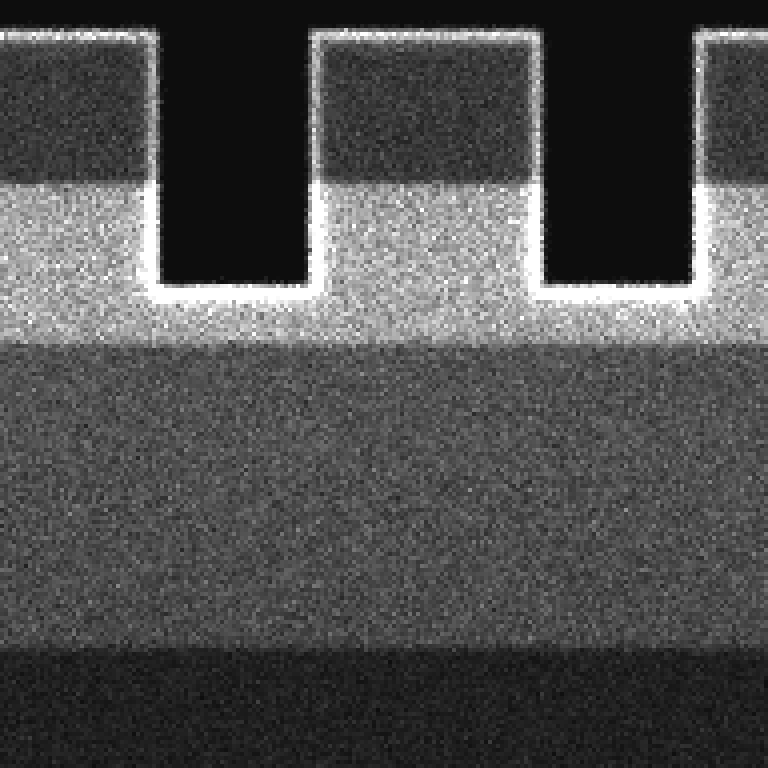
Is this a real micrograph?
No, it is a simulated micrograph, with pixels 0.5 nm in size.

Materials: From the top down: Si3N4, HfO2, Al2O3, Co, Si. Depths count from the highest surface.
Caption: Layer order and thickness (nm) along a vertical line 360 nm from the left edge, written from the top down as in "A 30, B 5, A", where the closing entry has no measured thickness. Si3N4 76, HfO2 80, Al2O3 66, Co 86, Si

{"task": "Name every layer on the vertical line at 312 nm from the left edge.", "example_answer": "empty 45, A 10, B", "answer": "empty 128, HfO2 28, Al2O3 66, Co 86, Si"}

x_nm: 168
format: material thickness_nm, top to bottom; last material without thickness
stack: Si3N4 76, HfO2 80, Al2O3 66, Co 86, Si